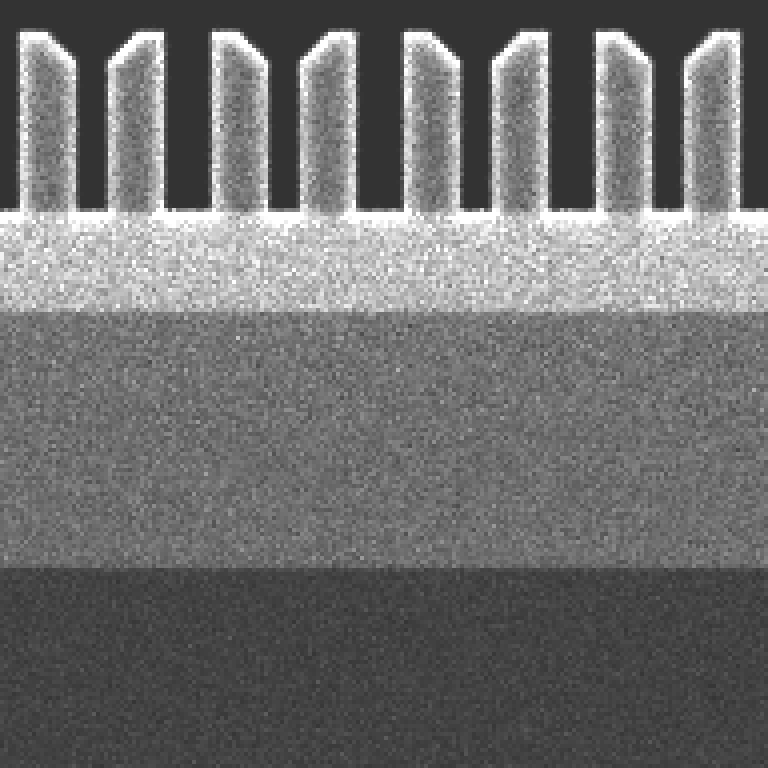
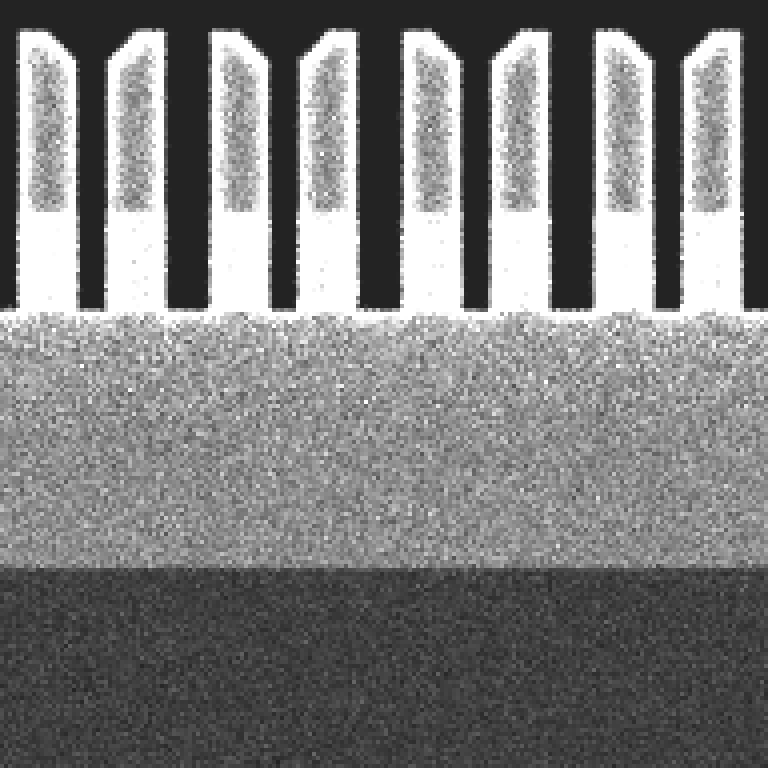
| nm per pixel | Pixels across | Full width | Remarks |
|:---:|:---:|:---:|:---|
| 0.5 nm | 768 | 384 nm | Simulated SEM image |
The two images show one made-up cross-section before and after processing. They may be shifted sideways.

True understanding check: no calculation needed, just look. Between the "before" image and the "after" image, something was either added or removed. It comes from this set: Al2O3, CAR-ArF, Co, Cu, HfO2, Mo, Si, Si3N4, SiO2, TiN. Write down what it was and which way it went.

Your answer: HfO2 (removed)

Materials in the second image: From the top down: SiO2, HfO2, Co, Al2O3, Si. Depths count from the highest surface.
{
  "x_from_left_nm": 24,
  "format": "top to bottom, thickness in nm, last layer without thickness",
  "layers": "empty 2, SiO2 88, HfO2 50, Co 54, Al2O3 74, Si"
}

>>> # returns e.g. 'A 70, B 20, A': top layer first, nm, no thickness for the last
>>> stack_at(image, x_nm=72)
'SiO2 90, HfO2 50, Co 54, Al2O3 74, Si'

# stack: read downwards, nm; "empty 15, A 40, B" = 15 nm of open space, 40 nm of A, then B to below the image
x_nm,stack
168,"SiO2 90, HfO2 50, Co 54, Al2O3 74, Si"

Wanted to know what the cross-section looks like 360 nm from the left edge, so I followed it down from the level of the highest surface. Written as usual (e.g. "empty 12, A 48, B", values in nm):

SiO2 90, HfO2 50, Co 54, Al2O3 74, Si